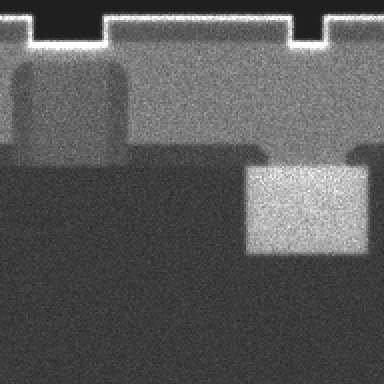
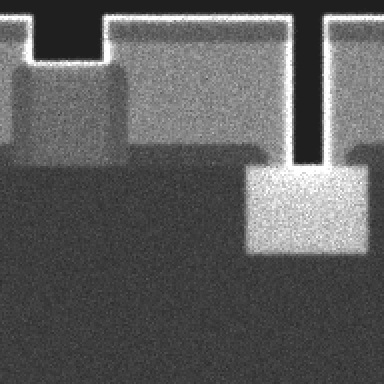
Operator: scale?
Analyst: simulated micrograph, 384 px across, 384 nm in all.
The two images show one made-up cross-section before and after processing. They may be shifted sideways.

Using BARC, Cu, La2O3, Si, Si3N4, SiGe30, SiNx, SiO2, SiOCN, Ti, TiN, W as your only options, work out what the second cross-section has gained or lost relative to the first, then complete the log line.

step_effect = removed SiO2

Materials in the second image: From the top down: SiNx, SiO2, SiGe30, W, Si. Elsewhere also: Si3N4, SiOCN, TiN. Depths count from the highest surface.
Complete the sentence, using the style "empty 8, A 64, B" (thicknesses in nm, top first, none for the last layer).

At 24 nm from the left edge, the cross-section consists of SiNx 26, SiO2 20, SiOCN 104, Si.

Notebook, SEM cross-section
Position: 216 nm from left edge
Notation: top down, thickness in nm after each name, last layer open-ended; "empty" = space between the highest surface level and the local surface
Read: SiNx 26, SiO2 102, SiGe30 22, Si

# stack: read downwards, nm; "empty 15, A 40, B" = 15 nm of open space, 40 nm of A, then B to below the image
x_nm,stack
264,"SiNx 26, SiO2 110, SiGe30 14, W 88, Si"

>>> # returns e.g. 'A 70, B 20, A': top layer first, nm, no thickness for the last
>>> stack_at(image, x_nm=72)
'empty 46, TiN 96, Si3N4 8, Si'